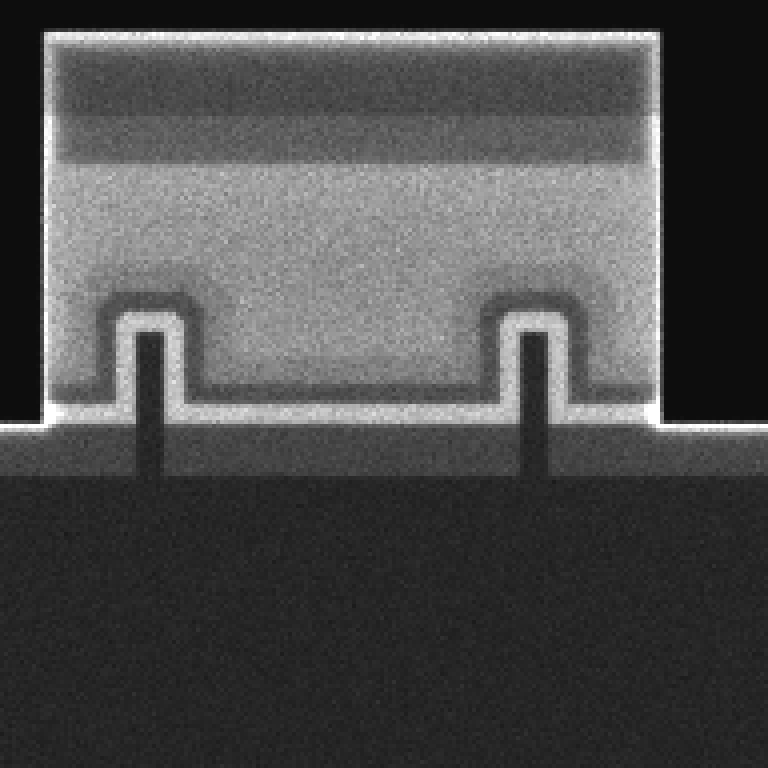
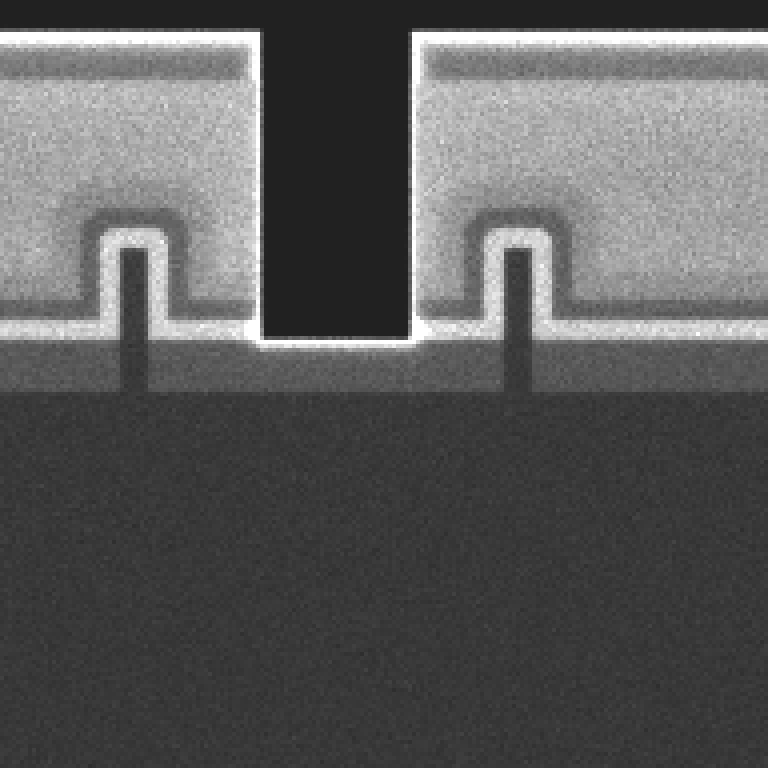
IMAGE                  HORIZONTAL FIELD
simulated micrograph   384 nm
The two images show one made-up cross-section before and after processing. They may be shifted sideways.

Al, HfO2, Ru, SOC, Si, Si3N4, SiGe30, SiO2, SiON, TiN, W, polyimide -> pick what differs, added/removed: SOC removed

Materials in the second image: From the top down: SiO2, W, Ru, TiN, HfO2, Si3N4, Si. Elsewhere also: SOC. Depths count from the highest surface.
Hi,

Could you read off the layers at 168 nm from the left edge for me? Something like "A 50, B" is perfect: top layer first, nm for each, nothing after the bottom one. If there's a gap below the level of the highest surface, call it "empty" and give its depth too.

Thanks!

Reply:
empty 154, Si3N4 26, Si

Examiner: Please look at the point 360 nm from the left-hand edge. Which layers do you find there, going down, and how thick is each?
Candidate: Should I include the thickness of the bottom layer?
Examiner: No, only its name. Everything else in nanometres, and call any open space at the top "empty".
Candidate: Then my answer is SiO2 24, W 96, Ru 14, TiN 10, HfO2 10, Si3N4 26, Si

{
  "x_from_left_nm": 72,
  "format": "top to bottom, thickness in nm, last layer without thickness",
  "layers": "SiO2 24, W 50, Ru 14, TiN 10, HfO2 10, Si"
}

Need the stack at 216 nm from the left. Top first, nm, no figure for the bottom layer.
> SiO2 24, W 96, Ru 14, TiN 10, HfO2 10, Si3N4 26, Si